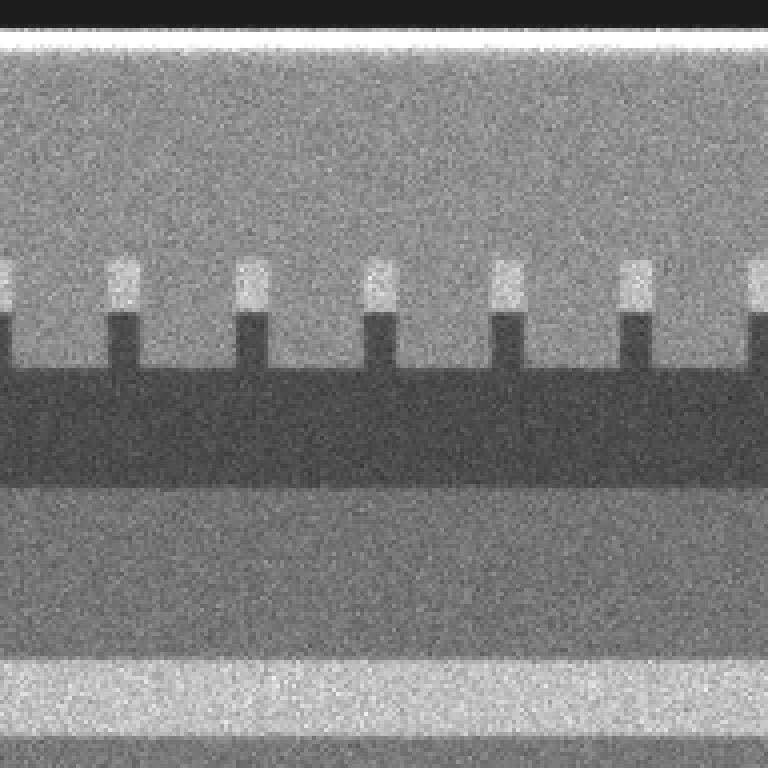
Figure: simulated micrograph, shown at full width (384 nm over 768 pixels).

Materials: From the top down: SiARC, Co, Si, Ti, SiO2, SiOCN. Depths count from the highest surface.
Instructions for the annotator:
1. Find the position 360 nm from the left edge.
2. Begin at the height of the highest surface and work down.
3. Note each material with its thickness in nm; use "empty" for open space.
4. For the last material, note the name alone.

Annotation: SiARC 168, Si 60, Ti 86, SiO2 38, SiOCN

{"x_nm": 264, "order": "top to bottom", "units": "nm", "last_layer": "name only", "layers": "SiARC 168, Si 60, Ti 86, SiO2 38, SiOCN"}